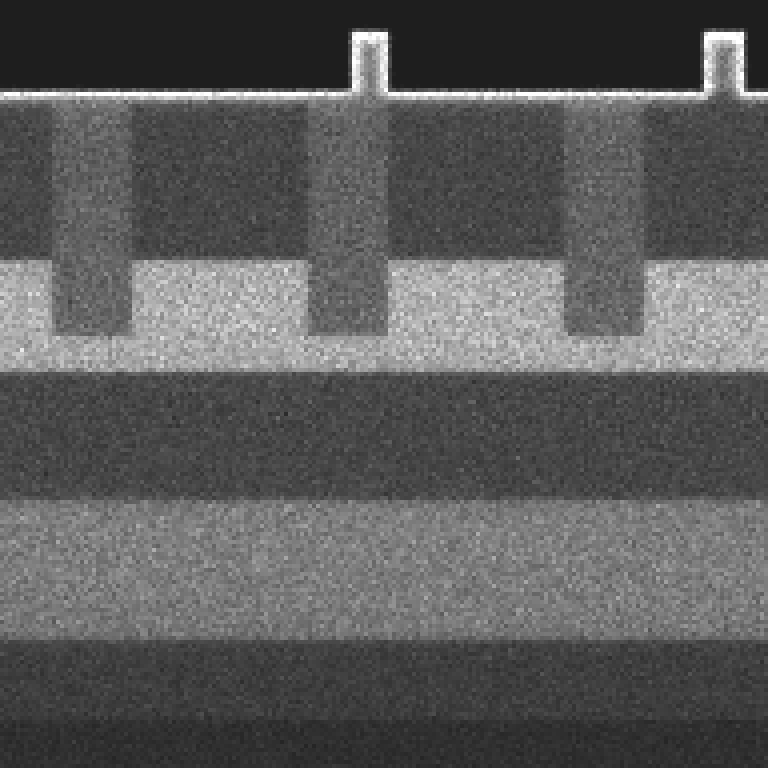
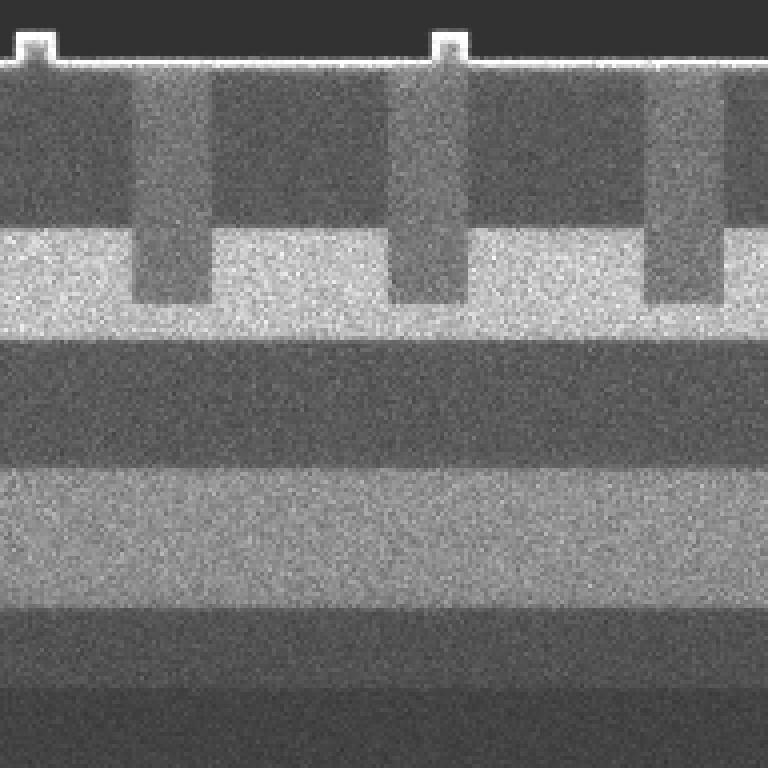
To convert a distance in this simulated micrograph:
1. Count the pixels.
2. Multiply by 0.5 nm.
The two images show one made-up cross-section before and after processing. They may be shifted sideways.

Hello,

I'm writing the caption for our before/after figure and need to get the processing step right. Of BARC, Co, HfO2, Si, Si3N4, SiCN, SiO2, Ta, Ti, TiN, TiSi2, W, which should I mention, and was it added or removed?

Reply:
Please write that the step removed SiO2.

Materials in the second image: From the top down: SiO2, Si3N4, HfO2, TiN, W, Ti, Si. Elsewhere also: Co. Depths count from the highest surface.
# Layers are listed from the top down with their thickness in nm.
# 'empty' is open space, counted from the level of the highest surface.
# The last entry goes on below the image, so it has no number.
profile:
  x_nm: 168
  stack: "empty 14, Si3N4 84, HfO2 56, TiN 64, W 70, Ti 40, Si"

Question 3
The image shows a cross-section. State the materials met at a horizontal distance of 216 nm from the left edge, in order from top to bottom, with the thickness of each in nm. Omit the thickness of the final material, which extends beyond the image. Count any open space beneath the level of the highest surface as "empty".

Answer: SiO2 14, Co 122, HfO2 18, TiN 64, W 70, Ti 40, Si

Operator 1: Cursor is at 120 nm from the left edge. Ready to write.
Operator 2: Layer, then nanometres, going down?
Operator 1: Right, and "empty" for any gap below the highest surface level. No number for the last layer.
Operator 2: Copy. empty 14, Si3N4 84, HfO2 56, TiN 64, W 70, Ti 40, Si